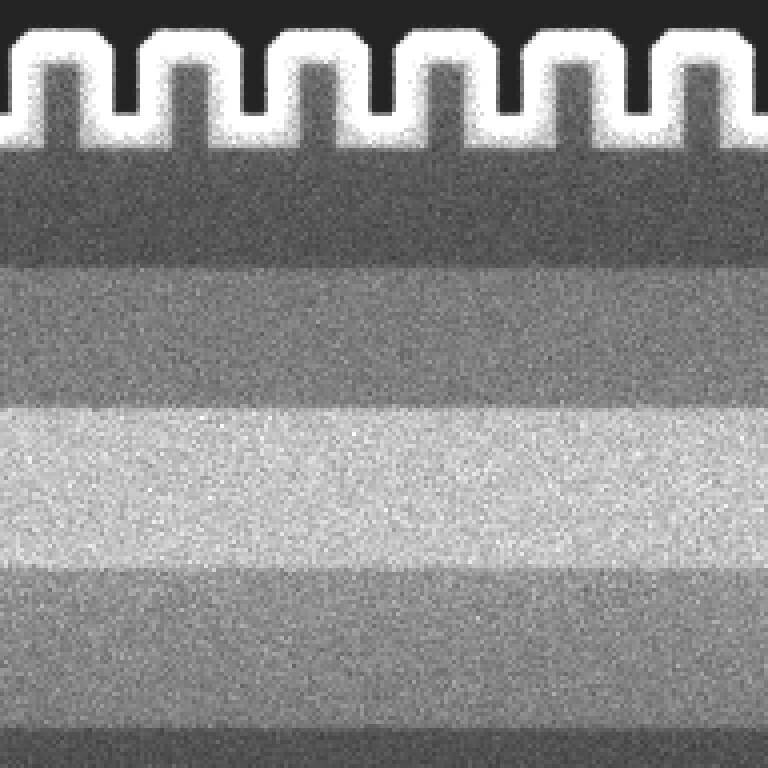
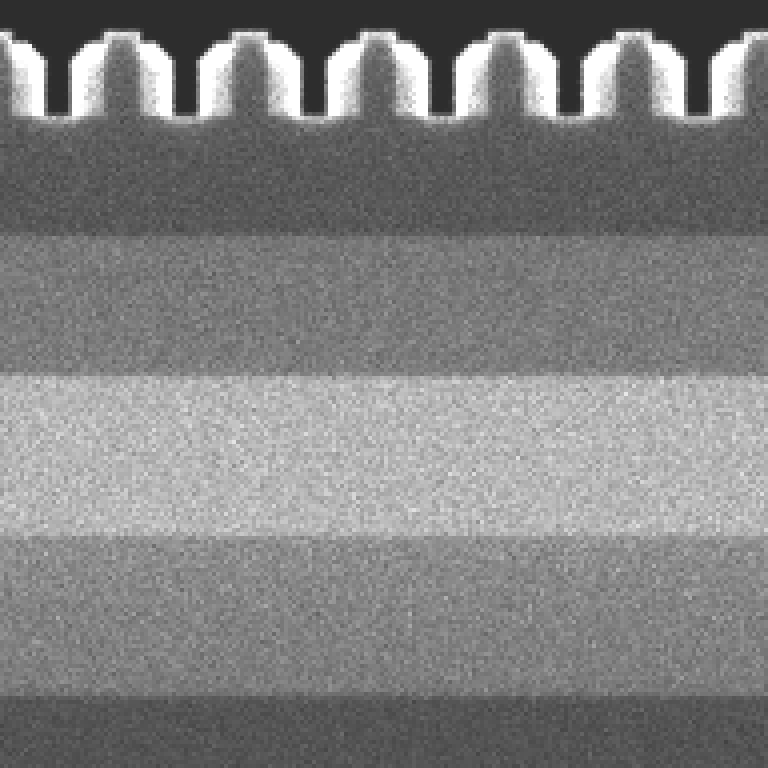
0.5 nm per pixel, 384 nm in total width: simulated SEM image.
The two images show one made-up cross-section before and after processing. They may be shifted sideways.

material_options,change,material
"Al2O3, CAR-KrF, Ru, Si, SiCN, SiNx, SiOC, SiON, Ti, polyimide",removed,Al2O3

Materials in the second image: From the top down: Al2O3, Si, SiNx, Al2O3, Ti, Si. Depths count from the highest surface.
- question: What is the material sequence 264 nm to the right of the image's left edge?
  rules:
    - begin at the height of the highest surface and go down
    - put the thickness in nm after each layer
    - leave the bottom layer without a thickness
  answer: empty 6, Al2O3 36, Si 60, SiNx 70, Al2O3 80, Ti 80, Si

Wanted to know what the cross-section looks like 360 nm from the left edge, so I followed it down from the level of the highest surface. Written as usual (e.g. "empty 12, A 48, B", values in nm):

empty 10, Al2O3 32, Si 60, SiNx 70, Al2O3 80, Ti 80, Si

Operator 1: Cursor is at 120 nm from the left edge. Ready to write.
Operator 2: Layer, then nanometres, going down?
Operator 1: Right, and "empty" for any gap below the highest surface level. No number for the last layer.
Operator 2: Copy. Si 102, SiNx 70, Al2O3 80, Ti 80, Si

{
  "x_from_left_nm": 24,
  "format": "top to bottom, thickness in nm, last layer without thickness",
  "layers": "empty 42, Si 60, SiNx 70, Al2O3 80, Ti 80, Si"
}